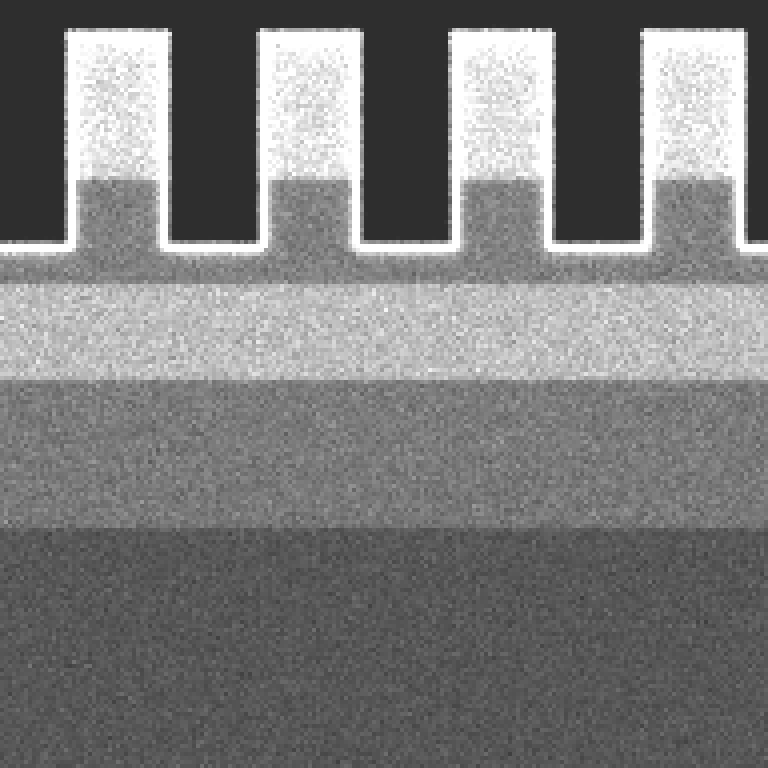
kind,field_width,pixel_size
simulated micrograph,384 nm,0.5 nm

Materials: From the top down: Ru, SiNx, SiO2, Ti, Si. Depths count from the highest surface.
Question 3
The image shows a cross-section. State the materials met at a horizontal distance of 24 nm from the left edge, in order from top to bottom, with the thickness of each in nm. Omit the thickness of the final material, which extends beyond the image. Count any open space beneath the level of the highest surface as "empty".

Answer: empty 106, SiNx 20, SiO2 48, Ti 74, Si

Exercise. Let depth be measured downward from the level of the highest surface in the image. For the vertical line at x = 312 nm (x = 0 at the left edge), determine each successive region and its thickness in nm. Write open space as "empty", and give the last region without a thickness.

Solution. empty 106, SiNx 20, SiO2 48, Ti 74, Si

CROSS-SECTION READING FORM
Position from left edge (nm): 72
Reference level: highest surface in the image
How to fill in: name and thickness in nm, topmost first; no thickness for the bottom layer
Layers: Ru 74, SiNx 52, SiO2 48, Ti 74, Si